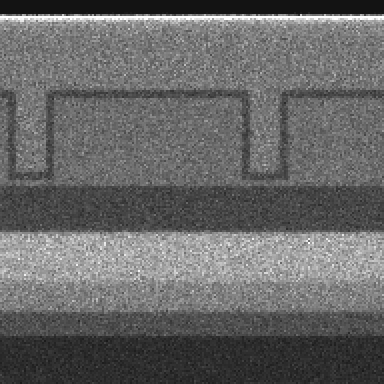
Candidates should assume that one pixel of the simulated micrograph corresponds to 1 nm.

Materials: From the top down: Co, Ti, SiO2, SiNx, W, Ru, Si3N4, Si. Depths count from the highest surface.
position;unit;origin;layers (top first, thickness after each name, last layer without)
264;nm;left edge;Co 156, Ti 8, SiO2 6, SiNx 46, W 50, Ru 30, Si3N4 24, Si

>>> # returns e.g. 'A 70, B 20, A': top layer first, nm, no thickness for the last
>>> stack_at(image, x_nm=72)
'Co 74, Ti 8, SiO2 88, SiNx 46, W 50, Ru 30, Si3N4 24, Si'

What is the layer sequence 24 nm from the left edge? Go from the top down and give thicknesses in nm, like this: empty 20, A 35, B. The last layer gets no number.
Co 156, Ti 8, SiO2 6, SiNx 46, W 50, Ru 30, Si3N4 24, Si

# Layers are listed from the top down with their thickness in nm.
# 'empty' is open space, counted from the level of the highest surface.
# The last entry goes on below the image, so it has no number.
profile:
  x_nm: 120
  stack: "Co 74, Ti 8, SiO2 88, SiNx 46, W 50, Ru 30, Si3N4 24, Si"